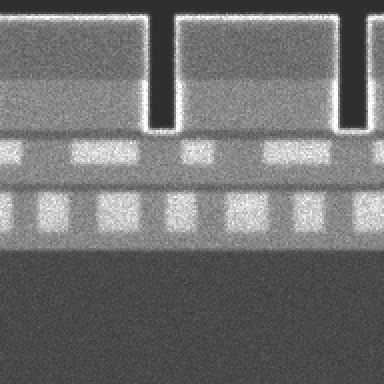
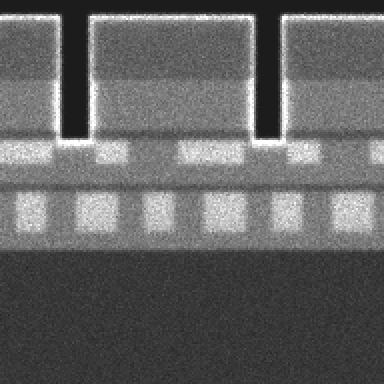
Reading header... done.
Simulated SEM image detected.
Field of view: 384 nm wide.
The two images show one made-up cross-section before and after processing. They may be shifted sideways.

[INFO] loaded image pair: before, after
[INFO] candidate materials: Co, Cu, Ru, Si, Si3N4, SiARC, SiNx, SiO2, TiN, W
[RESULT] removed SiNx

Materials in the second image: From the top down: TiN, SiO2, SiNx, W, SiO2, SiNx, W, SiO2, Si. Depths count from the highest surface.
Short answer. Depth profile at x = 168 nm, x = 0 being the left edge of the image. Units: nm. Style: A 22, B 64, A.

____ TiN 64, SiO2 50, SiNx 10, SiO2 44, SiNx 8, W 40, SiO2 18, Si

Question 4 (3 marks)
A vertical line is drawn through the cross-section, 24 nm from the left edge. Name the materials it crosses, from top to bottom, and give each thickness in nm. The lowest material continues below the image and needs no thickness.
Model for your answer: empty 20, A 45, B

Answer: TiN 64, SiO2 50, SiNx 10, W 24, SiO2 20, SiNx 8, W 40, SiO2 18, Si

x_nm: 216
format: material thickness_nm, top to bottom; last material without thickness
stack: TiN 64, SiO2 50, SiNx 10, W 24, SiO2 20, SiNx 8, W 40, SiO2 18, Si